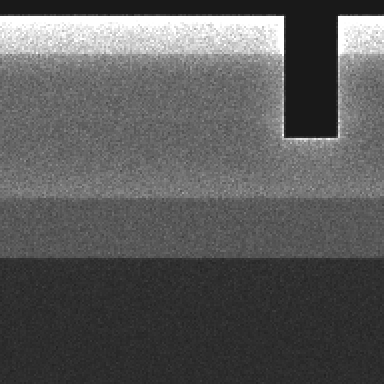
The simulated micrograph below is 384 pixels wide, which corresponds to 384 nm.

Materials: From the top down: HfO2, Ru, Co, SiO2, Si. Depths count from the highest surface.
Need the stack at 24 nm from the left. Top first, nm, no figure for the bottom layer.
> HfO2 38, Ru 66, Co 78, SiO2 60, Si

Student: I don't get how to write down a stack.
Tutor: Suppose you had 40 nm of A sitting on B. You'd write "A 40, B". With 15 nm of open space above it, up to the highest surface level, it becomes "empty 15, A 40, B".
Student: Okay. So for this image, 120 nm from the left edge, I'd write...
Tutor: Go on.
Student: HfO2 38, Ru 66, Co 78, SiO2 60, Si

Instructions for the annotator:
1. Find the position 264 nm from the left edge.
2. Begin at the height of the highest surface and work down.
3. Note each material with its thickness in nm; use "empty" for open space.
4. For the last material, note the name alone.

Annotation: HfO2 38, Ru 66, Co 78, SiO2 60, Si